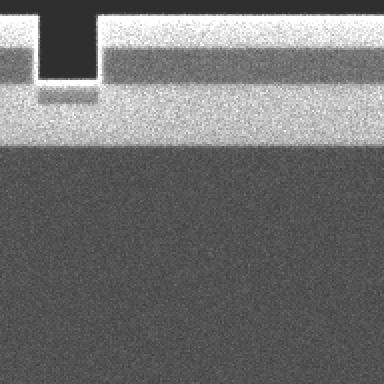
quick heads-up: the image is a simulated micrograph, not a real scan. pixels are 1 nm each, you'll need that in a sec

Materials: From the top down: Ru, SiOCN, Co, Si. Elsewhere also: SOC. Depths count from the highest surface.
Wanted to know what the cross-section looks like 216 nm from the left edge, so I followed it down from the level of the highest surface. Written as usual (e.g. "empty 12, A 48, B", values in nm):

Ru 32, SiOCN 36, Co 62, Si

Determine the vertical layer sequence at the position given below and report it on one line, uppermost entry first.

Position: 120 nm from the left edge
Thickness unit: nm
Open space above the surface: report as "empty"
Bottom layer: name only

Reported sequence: Ru 32, SiOCN 36, Co 62, Si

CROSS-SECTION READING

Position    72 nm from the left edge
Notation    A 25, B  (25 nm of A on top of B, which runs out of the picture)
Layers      empty 64, SOC 24, Co 42, Si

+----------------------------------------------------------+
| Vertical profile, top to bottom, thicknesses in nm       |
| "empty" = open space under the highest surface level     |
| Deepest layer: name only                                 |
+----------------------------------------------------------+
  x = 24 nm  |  Ru 32, SiOCN 36, Co 62, Si